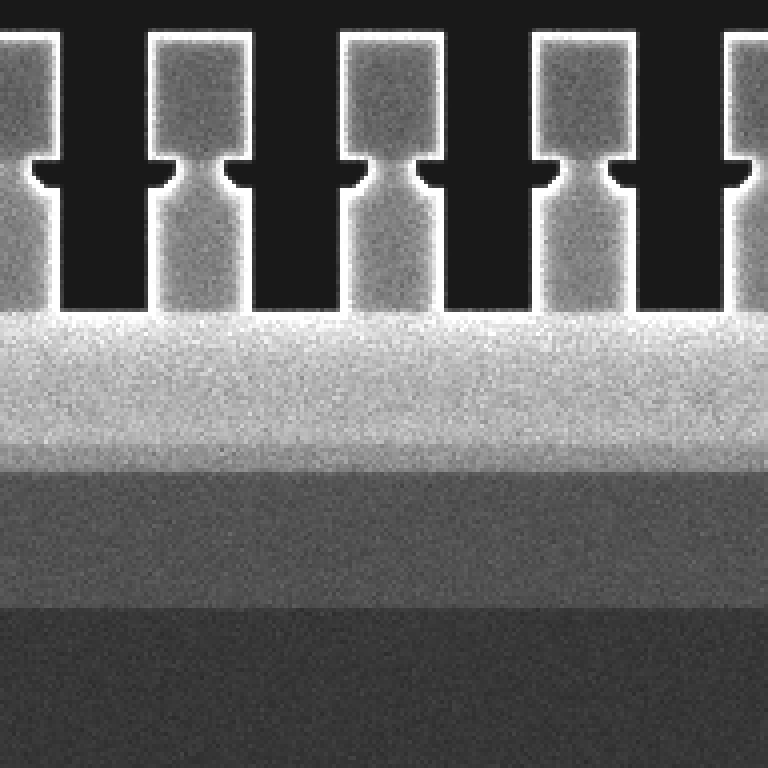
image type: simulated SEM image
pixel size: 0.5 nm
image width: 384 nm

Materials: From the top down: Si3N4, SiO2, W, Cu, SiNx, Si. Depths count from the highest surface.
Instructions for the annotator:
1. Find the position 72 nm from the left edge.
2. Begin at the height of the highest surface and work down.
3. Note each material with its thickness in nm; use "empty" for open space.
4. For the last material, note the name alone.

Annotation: empty 140, W 66, Cu 14, SiNx 68, Si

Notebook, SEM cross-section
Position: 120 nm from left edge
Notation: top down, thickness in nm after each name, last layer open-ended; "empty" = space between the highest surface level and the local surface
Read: Si3N4 64, empty 14, SiO2 62, W 66, Cu 14, SiNx 68, Si